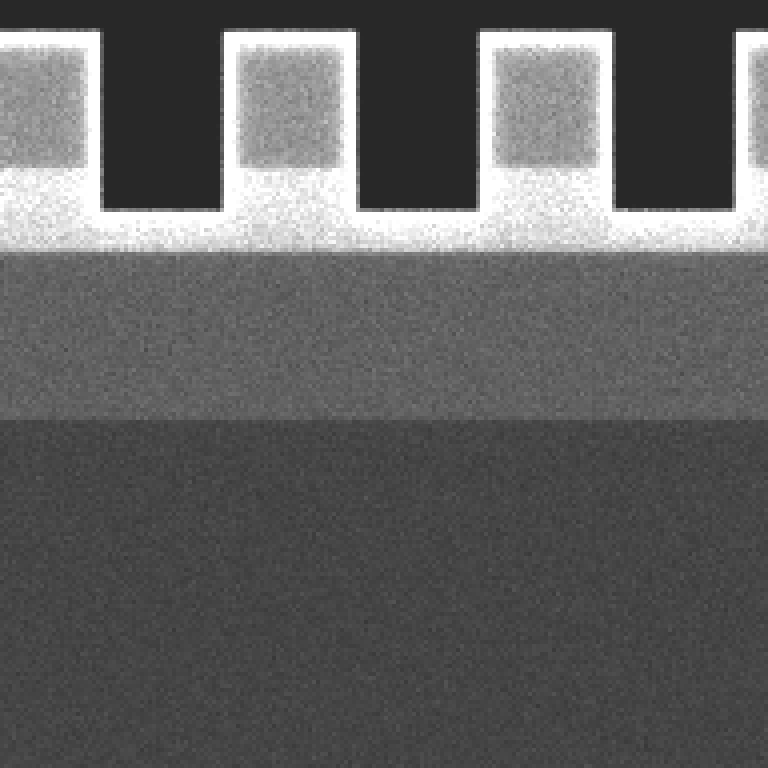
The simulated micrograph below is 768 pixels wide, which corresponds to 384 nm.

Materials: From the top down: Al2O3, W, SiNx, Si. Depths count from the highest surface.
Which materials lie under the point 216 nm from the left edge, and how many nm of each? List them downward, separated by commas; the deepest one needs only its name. empty 90, W 20, SiNx 84, Si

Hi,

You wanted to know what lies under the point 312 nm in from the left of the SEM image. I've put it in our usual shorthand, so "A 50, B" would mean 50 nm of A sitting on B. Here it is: empty 90, W 20, SiNx 84, Si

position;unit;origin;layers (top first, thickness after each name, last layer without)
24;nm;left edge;Al2O3 68, W 42, SiNx 84, Si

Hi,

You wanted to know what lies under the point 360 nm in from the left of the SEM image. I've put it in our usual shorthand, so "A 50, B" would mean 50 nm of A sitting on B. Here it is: empty 90, W 20, SiNx 84, Si